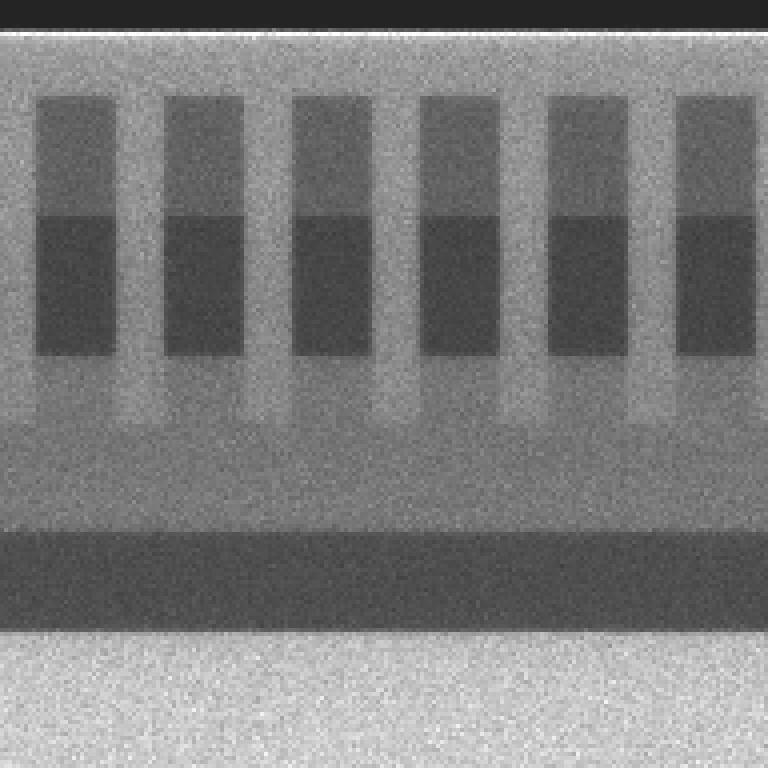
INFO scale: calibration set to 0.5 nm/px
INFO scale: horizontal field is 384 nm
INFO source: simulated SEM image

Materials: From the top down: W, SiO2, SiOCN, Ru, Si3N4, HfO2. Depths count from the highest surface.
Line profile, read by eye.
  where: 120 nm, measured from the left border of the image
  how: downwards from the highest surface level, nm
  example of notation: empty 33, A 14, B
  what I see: W 32, SiO2 60, SiOCN 70, Ru 88, Si3N4 50, HfO2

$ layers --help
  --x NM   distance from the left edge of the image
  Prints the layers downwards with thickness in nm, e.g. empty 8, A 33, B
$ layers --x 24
W 32, SiO2 60, SiOCN 70, Ru 88, Si3N4 50, HfO2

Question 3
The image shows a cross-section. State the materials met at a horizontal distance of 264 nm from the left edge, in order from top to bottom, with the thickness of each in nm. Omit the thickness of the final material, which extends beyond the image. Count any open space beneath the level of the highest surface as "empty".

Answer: W 196, Ru 54, Si3N4 50, HfO2